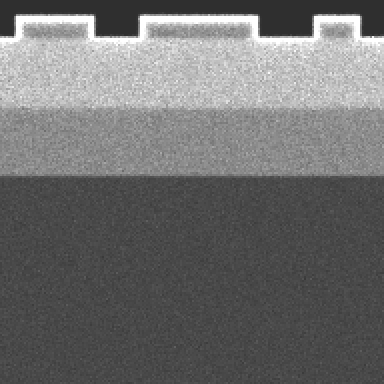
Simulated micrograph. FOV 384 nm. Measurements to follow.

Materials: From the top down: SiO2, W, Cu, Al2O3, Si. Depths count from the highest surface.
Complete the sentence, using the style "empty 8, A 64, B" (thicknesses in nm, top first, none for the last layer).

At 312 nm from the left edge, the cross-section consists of empty 22, W 70, Cu 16, Al2O3 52, Si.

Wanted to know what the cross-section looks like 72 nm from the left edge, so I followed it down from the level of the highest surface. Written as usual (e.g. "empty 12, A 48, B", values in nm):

SiO2 22, W 70, Cu 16, Al2O3 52, Si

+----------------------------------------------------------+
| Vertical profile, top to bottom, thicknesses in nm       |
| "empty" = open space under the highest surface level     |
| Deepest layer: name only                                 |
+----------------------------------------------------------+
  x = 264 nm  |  empty 22, W 70, Cu 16, Al2O3 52, Si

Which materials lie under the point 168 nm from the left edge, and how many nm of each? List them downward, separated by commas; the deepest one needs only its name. SiO2 22, W 70, Cu 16, Al2O3 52, Si